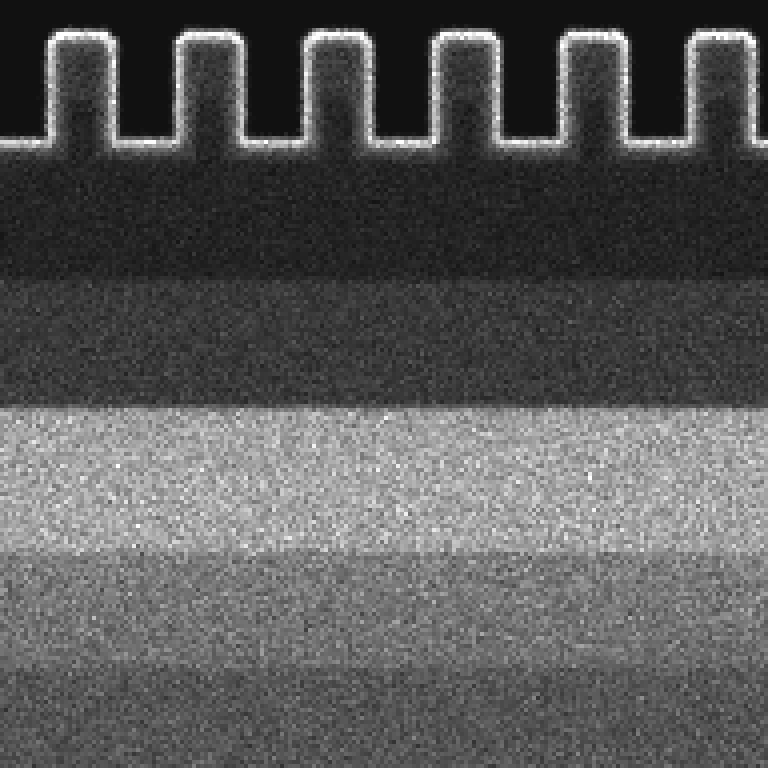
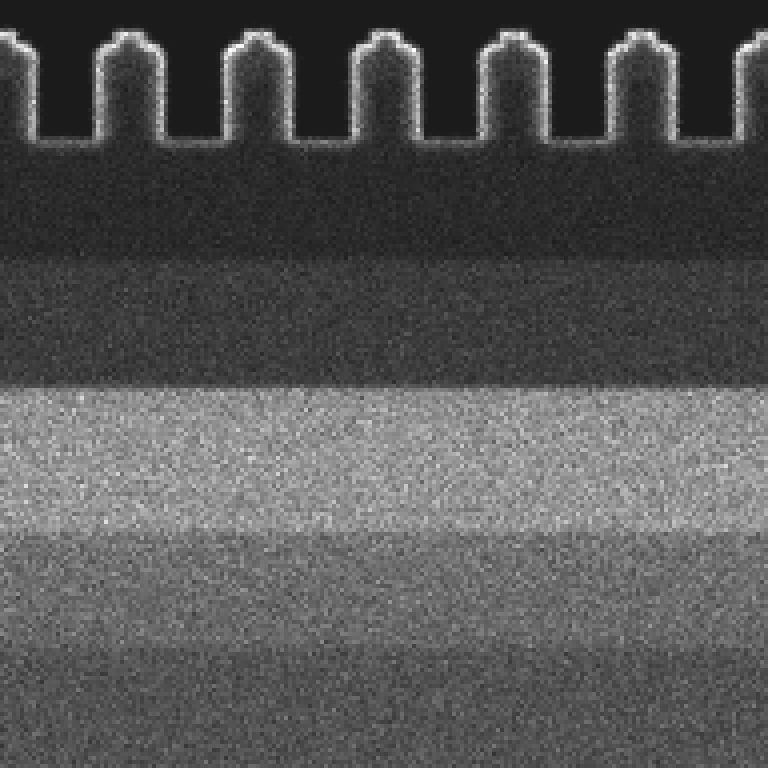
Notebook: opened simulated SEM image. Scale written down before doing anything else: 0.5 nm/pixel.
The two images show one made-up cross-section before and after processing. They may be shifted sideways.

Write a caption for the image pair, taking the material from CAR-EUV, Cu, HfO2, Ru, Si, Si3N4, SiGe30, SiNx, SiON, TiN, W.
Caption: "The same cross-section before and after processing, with Si3N4 removed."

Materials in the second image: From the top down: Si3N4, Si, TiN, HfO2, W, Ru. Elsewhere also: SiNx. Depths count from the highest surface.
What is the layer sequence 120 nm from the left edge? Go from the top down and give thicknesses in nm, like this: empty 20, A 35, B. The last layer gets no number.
empty 6, Si3N4 48, Si 60, TiN 64, HfO2 72, W 58, Ru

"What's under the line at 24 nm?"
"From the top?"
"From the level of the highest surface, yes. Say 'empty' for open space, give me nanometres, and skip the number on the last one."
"empty 54, Si 60, TiN 64, HfO2 72, W 58, Ru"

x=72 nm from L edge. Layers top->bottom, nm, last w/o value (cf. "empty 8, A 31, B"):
empty 6, Si3N4 48, Si 60, TiN 64, HfO2 72, W 58, Ru